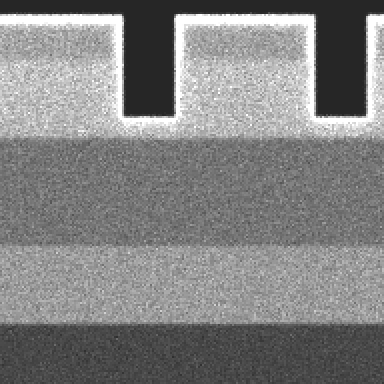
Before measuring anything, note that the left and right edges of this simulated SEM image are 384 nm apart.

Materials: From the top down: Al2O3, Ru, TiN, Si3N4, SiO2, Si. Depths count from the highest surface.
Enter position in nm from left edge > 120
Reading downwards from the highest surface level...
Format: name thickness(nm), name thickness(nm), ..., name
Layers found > Al2O3 44, Ru 78, TiN 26, Si3N4 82, SiO2 78, Si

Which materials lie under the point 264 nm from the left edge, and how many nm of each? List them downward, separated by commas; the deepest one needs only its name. Al2O3 44, Ru 78, TiN 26, Si3N4 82, SiO2 78, Si